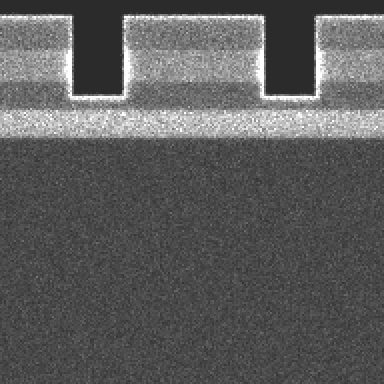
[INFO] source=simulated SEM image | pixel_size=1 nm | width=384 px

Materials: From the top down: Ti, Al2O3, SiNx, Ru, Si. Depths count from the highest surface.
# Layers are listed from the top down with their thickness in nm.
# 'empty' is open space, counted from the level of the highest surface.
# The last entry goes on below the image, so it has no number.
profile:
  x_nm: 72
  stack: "empty 80, SiNx 14, Ru 28, Si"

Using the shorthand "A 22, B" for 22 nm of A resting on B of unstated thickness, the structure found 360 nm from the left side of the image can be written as Ti 34, Al2O3 32, SiNx 28, Ru 28, Si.